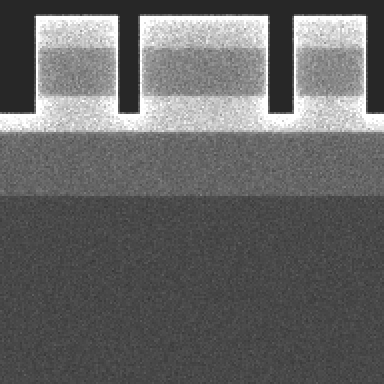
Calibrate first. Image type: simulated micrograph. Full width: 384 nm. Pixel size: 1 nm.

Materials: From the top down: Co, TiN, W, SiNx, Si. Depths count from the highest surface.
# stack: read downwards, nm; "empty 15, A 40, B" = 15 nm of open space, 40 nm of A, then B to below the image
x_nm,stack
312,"Co 32, TiN 48, W 36, SiNx 64, Si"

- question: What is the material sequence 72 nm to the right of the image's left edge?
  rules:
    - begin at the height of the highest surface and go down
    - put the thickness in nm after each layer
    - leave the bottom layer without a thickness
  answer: Co 32, TiN 48, W 36, SiNx 64, Si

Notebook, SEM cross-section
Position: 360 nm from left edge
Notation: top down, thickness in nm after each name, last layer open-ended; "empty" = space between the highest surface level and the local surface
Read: Co 32, TiN 48, W 36, SiNx 64, Si